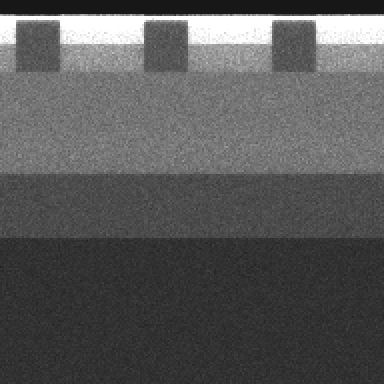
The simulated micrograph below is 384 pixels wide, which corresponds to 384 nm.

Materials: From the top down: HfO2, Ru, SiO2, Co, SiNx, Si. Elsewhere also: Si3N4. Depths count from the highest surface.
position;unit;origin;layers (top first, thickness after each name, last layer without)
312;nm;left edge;Si3N4 56, SiO2 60, Co 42, SiNx 64, Si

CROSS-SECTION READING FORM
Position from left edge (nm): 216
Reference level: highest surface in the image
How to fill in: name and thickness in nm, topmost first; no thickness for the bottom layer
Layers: HfO2 28, Ru 28, SiO2 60, Co 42, SiNx 64, Si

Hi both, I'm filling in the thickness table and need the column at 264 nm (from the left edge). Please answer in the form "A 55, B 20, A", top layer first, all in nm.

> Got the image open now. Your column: HfO2 28, Ru 28, SiO2 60, Co 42, SiNx 64, Si